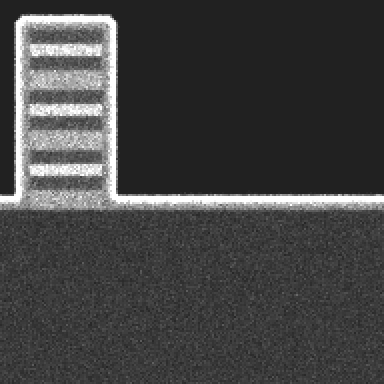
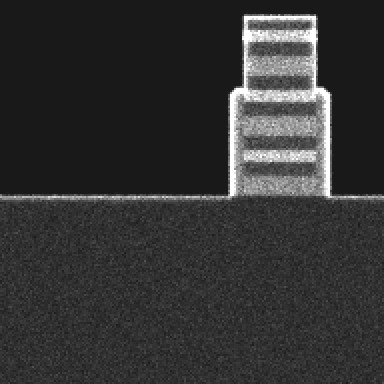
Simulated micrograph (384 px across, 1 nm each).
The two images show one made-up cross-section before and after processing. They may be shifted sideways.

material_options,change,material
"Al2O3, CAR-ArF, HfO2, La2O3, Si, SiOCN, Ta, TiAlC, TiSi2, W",removed,Al2O3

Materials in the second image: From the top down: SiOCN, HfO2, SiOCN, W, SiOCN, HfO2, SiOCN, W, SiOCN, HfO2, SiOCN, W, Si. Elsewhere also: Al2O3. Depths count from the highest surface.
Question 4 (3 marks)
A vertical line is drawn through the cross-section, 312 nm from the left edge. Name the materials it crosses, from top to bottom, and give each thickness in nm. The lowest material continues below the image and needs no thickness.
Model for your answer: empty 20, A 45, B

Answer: SiOCN 14, HfO2 12, SiOCN 14, W 20, SiOCN 14, HfO2 12, SiOCN 14, W 20, SiOCN 14, HfO2 12, SiOCN 14, W 20, Si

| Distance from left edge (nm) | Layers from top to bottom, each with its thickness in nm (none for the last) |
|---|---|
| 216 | empty 180, Si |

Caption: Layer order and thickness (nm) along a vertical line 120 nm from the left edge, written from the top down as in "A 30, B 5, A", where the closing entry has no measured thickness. empty 180, Si